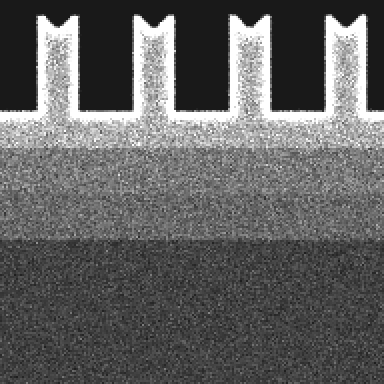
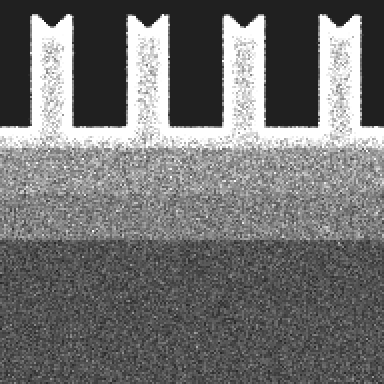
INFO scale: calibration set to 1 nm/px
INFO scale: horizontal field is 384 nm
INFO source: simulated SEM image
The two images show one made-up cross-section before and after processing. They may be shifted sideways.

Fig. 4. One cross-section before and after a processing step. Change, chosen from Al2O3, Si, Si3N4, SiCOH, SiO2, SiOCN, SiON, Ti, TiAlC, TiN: Al2O3 removed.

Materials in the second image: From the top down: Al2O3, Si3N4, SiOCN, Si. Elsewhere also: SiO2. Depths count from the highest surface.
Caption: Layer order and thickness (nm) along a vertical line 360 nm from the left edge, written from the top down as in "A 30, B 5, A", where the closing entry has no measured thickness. empty 112, Al2O3 20, Si3N4 46, SiOCN 46, Si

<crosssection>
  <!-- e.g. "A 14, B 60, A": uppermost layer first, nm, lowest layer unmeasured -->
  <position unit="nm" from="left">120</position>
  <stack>empty 112, Al2O3 20, Si3N4 46, SiOCN 46, Si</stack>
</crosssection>